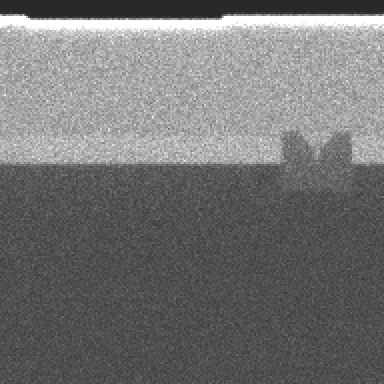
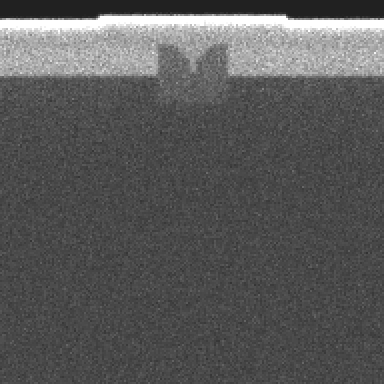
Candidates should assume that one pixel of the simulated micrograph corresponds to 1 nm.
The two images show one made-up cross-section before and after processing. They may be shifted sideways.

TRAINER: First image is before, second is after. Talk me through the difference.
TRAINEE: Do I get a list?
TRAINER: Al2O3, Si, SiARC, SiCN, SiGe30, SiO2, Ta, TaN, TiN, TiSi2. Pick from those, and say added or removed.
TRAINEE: removed: SiO2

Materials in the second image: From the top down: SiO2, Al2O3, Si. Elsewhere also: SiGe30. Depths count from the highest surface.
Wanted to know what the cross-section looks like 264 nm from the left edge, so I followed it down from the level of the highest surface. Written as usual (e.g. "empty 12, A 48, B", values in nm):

SiO2 32, Al2O3 28, Si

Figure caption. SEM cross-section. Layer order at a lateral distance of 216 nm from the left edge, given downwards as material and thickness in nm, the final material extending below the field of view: SiO2 28, SiGe30 60, Si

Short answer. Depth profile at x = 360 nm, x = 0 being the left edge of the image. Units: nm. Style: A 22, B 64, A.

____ empty 4, SiO2 28, Al2O3 28, Si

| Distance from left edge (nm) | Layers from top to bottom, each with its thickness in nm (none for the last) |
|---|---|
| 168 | SiO2 28, SiGe30 60, Si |